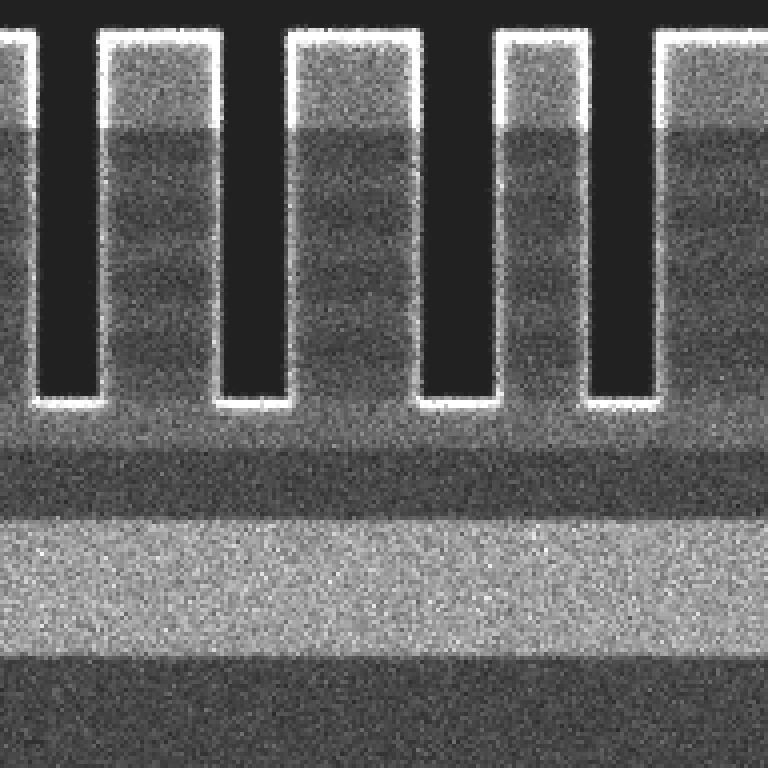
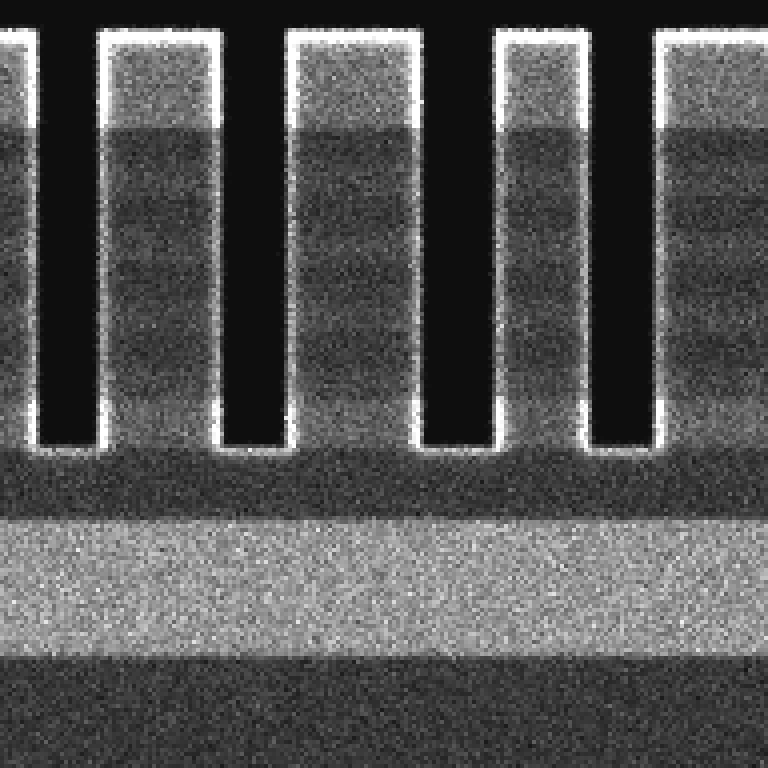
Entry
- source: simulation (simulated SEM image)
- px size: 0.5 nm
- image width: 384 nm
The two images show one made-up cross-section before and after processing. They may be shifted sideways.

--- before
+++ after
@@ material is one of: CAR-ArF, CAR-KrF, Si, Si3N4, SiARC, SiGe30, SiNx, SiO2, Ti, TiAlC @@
SiNx removed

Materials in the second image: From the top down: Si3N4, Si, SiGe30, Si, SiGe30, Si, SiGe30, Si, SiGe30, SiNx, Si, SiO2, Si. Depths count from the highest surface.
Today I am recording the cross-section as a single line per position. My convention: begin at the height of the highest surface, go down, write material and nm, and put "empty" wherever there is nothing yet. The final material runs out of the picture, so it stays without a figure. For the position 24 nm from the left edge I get empty 208, Si 36, SiO2 68, Si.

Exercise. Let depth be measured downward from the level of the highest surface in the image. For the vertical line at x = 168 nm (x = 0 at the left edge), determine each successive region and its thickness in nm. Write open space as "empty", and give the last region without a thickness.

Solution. Si3N4 48, Si 18, SiGe30 16, Si 18, SiGe30 16, Si 18, SiGe30 16, Si 18, SiGe30 16, SiNx 24, Si 36, SiO2 68, Si